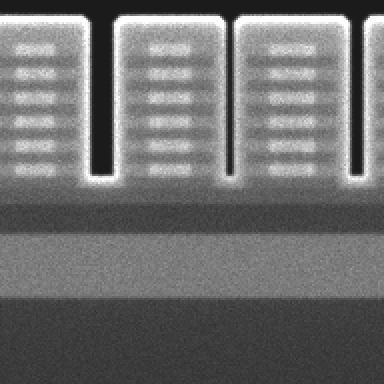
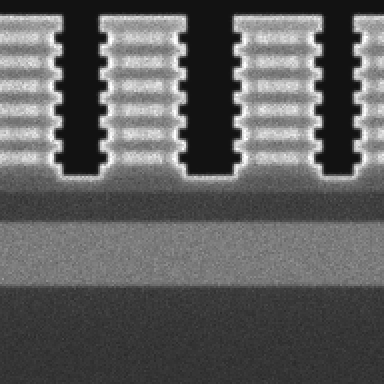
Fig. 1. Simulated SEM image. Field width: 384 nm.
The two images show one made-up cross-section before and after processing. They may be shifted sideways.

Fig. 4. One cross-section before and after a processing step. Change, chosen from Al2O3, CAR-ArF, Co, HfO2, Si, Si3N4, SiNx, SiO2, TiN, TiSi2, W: Al2O3 removed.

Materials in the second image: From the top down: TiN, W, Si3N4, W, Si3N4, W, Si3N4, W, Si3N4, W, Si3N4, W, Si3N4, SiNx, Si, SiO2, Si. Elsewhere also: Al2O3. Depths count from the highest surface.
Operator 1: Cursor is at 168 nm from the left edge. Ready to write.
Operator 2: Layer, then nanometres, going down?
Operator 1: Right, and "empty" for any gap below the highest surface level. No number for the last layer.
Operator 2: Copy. TiN 16, Al2O3 12, Si3N4 12, Al2O3 12, Si3N4 12, Al2O3 12, Si3N4 12, Al2O3 12, Si3N4 12, Al2O3 12, Si3N4 12, Al2O3 12, Si3N4 12, SiNx 16, Si 30, SiO2 64, Si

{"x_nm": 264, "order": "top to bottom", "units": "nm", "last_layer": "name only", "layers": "TiN 16, W 12, Si3N4 12, W 12, Si3N4 12, W 12, Si3N4 12, W 12, Si3N4 12, W 12, Si3N4 12, W 12, Si3N4 12, SiNx 16, Si 30, SiO2 64, Si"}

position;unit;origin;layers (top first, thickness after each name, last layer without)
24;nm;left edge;TiN 16, W 12, Si3N4 12, W 12, Si3N4 12, W 12, Si3N4 12, W 12, Si3N4 12, W 12, Si3N4 12, W 12, Si3N4 12, SiNx 16, Si 30, SiO2 64, Si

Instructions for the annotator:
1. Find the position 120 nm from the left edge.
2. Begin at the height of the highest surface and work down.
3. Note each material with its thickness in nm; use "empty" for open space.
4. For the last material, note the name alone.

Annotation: TiN 16, Al2O3 12, Si3N4 12, Al2O3 12, Si3N4 12, Al2O3 12, Si3N4 12, Al2O3 12, Si3N4 12, Al2O3 12, Si3N4 12, Al2O3 12, Si3N4 12, SiNx 16, Si 30, SiO2 64, Si